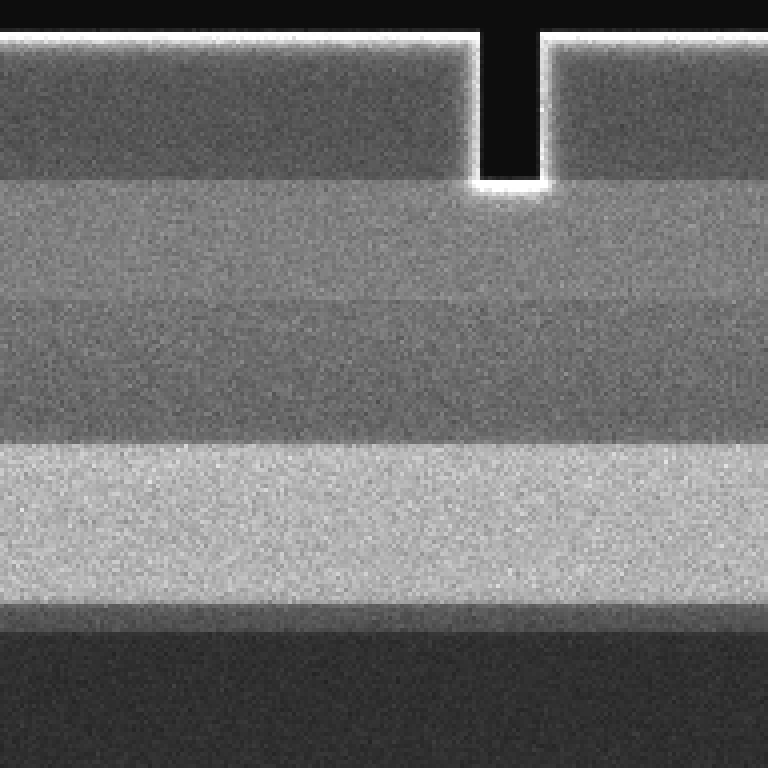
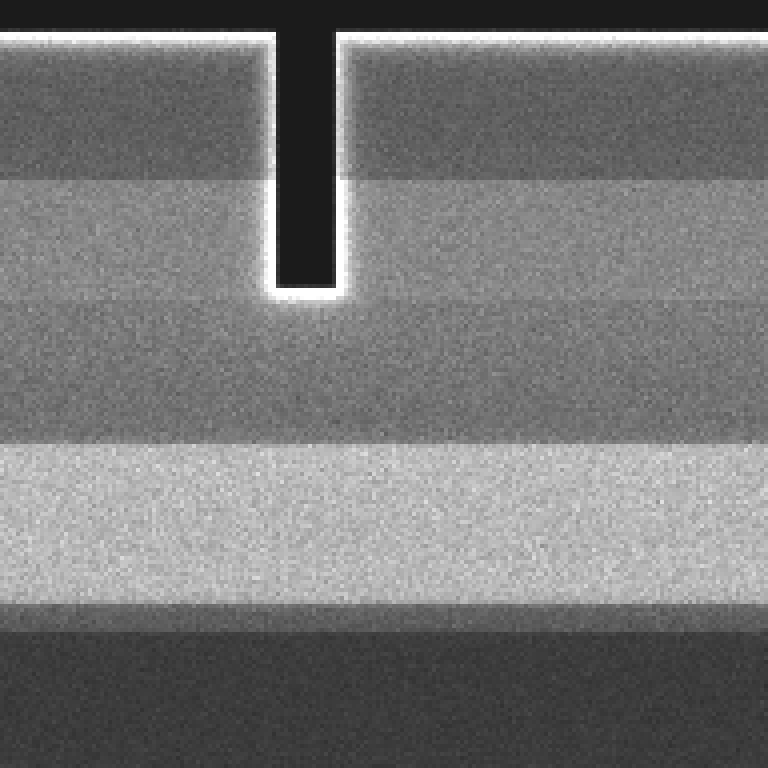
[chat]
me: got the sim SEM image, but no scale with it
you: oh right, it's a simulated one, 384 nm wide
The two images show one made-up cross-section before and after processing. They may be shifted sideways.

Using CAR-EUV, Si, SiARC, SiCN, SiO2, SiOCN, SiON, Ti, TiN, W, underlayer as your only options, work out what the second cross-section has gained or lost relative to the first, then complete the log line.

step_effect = removed SiO2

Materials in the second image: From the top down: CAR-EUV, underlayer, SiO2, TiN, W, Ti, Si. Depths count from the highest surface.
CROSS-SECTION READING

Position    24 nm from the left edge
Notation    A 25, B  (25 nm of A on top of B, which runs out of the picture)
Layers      CAR-EUV 58, underlayer 16, SiO2 60, TiN 72, W 80, Ti 14, Si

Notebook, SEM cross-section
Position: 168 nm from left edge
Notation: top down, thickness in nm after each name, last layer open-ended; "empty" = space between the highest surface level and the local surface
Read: CAR-EUV 58, underlayer 16, SiO2 60, TiN 72, W 80, Ti 14, Si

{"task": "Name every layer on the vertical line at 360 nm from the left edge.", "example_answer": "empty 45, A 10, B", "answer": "CAR-EUV 58, underlayer 16, SiO2 60, TiN 72, W 80, Ti 14, Si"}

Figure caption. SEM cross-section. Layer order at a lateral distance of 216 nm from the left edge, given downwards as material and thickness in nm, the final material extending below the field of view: CAR-EUV 58, underlayer 16, SiO2 60, TiN 72, W 80, Ti 14, Si